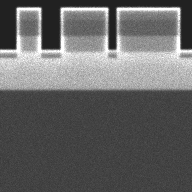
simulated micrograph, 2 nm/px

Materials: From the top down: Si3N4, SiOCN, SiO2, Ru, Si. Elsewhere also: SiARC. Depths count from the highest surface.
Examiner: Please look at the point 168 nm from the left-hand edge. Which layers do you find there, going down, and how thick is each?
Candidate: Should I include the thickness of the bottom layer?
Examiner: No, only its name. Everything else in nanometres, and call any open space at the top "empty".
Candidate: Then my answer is Si3N4 24, SiOCN 32, SiO2 32, Ru 76, Si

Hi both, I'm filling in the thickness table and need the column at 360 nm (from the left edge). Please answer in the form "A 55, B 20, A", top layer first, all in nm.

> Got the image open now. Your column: empty 84, SiARC 16, Ru 64, Si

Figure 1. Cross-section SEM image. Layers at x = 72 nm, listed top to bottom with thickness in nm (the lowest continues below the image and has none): Si3N4 24, SiOCN 32, SiO2 32, Ru 76, Si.